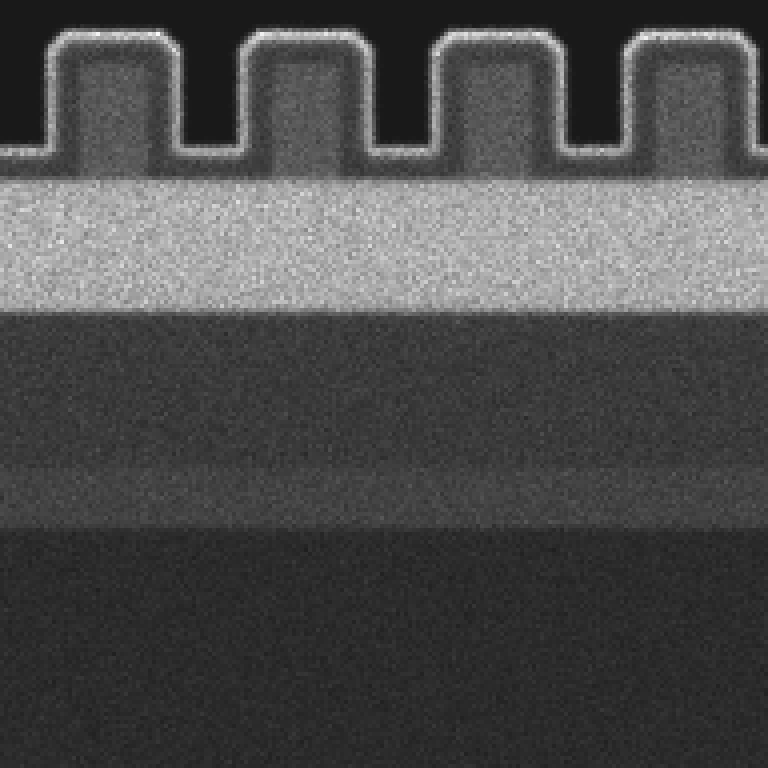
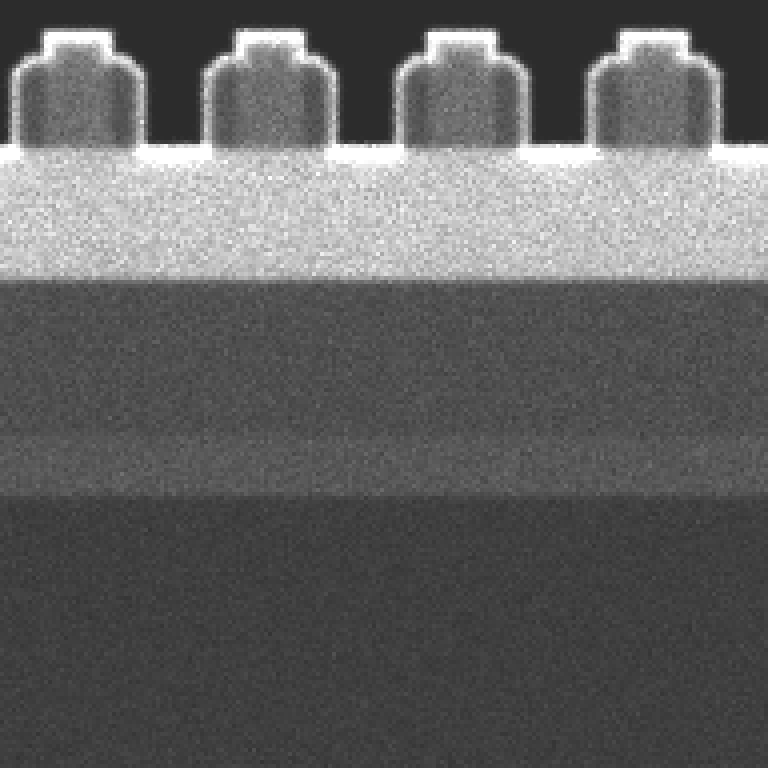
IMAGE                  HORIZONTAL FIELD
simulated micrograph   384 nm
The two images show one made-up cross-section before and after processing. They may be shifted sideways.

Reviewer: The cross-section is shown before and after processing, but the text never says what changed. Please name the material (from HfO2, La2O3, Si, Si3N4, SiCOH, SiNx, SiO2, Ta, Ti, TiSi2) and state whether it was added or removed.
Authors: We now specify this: SiNx, removed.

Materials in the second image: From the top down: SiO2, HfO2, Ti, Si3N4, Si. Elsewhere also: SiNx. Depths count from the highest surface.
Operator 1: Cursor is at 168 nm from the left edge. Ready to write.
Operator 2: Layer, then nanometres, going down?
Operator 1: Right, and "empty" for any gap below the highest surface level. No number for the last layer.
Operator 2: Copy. empty 58, HfO2 66, Ti 78, Si3N4 30, Si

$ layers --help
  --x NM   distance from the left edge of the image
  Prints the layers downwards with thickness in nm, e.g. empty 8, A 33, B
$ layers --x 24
SiO2 58, HfO2 66, Ti 78, Si3N4 30, Si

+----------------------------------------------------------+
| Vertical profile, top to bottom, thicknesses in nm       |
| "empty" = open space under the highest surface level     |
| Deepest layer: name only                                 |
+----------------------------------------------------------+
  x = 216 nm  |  SiO2 58, HfO2 66, Ti 78, Si3N4 30, Si